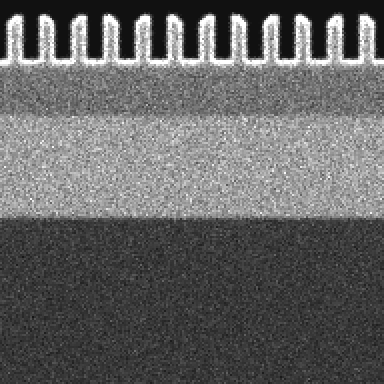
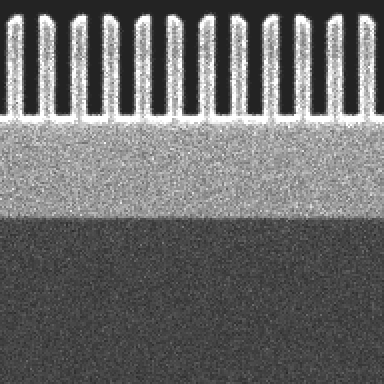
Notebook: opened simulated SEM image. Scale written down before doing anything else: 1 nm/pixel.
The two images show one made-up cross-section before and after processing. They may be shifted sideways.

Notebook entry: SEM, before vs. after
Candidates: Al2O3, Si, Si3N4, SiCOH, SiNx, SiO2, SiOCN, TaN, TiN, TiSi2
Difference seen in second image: Si3N4 removed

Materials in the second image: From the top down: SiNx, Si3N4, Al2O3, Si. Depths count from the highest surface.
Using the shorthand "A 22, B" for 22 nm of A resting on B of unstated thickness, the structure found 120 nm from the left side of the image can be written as empty 100, Al2O3 102, Si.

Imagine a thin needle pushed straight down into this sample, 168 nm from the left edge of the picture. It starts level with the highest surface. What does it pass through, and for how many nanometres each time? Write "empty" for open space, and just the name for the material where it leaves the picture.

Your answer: SiNx 44, Si3N4 56, Al2O3 102, Si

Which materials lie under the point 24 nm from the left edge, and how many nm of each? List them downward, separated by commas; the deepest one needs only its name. empty 100, Al2O3 102, Si